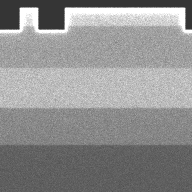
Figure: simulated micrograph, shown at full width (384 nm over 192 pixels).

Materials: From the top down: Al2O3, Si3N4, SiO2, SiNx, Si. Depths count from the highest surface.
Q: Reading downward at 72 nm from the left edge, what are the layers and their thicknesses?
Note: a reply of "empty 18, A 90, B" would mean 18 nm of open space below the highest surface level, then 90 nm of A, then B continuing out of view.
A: Al2O3 36, Si3N4 84, SiO2 80, SiNx 74, Si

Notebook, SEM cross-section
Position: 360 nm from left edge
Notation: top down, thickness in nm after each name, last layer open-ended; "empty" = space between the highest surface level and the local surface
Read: Al2O3 36, Si3N4 84, SiO2 80, SiNx 74, Si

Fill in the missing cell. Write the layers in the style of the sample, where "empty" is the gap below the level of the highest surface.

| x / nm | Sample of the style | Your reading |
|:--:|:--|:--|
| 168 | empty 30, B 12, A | Al2O3 36, Si3N4 84, SiO2 80, SiNx 74, Si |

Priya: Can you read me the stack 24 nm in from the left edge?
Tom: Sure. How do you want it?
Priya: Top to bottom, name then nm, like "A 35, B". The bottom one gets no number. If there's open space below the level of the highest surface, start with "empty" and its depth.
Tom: empty 44, Si3N4 76, SiO2 80, SiNx 74, Si